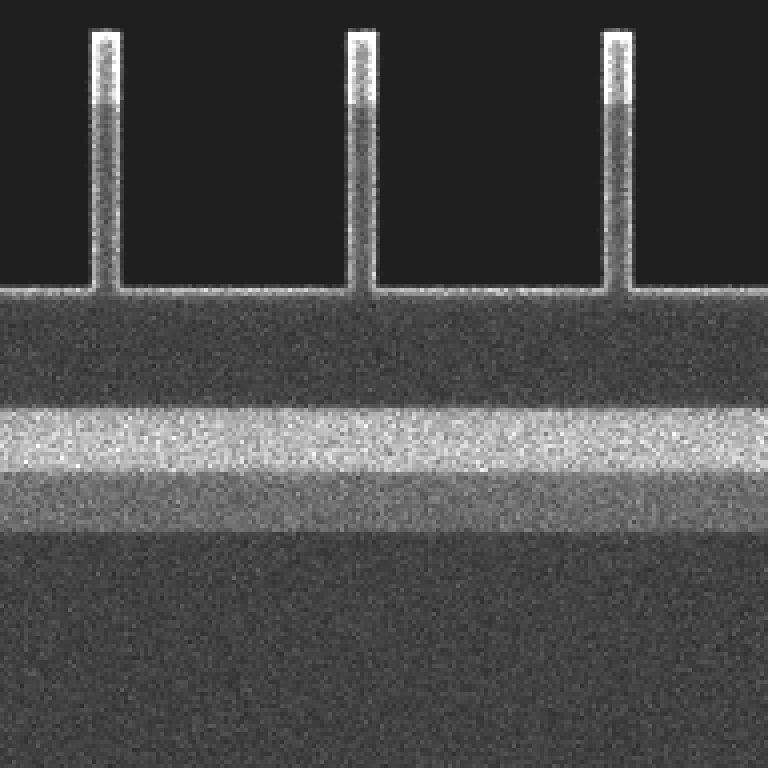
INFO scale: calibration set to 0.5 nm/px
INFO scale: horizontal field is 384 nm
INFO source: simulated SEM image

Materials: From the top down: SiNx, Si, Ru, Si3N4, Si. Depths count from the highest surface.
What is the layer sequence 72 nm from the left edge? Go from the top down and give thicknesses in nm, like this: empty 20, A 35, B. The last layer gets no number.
empty 128, Si 60, Ru 32, Si3N4 30, Si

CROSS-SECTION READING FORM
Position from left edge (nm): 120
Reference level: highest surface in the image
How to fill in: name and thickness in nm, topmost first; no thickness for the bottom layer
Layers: empty 128, Si 60, Ru 32, Si3N4 30, Si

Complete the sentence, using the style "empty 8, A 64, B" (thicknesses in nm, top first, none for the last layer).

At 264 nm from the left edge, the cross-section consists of empty 128, Si 60, Ru 32, Si3N4 30, Si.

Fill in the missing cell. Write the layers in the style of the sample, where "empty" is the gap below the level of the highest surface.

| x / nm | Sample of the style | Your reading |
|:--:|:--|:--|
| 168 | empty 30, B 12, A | empty 128, Si 60, Ru 32, Si3N4 30, Si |